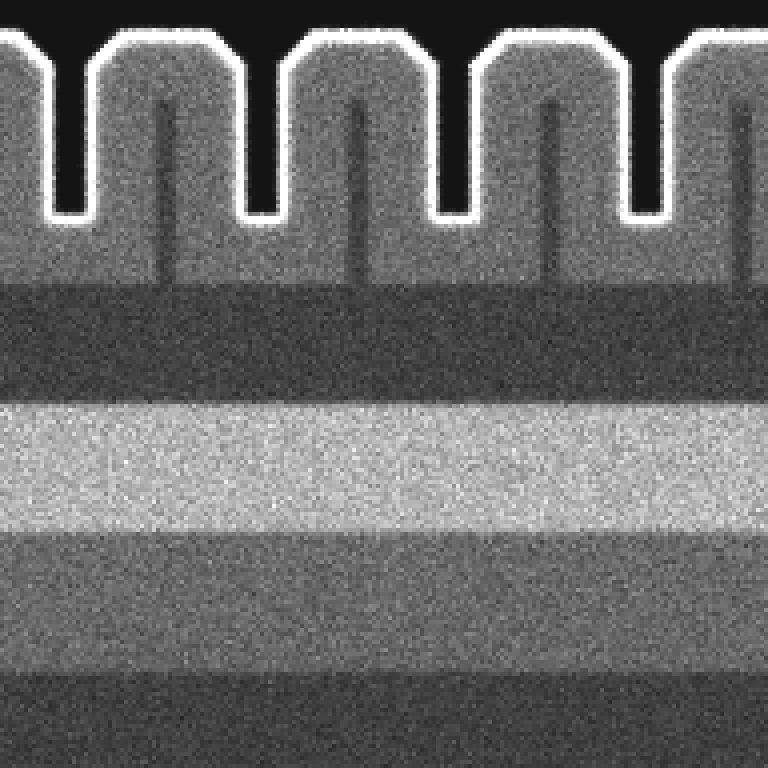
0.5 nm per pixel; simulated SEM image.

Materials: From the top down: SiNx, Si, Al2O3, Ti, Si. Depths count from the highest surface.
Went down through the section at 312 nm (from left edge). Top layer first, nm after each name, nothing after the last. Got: empty 16, SiNx 110, Si 60, Al2O3 64, Ti 70, Si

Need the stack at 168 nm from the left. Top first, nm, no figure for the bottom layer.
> SiNx 126, Si 60, Al2O3 64, Ti 70, Si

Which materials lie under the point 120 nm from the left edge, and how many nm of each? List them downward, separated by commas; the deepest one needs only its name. empty 16, SiNx 110, Si 60, Al2O3 64, Ti 70, Si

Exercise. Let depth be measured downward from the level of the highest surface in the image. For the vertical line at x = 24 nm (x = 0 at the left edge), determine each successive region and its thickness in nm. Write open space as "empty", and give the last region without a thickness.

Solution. empty 16, SiNx 110, Si 60, Al2O3 64, Ti 70, Si